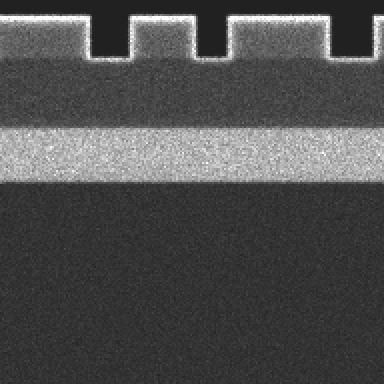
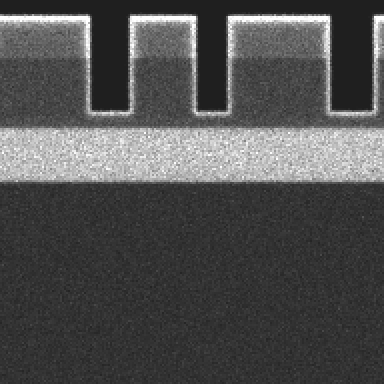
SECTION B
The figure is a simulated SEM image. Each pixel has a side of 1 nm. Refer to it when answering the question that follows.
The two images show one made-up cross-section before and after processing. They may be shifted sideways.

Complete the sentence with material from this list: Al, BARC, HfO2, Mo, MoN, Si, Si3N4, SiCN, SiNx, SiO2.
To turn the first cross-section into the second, SiNx must be removed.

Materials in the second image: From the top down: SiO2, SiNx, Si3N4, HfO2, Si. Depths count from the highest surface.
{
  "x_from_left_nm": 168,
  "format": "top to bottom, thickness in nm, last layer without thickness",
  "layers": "SiO2 42, SiNx 60, Si3N4 10, HfO2 54, Si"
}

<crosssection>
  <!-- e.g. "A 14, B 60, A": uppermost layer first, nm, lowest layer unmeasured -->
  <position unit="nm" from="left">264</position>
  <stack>SiO2 42, SiNx 60, Si3N4 10, HfO2 54, Si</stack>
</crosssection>